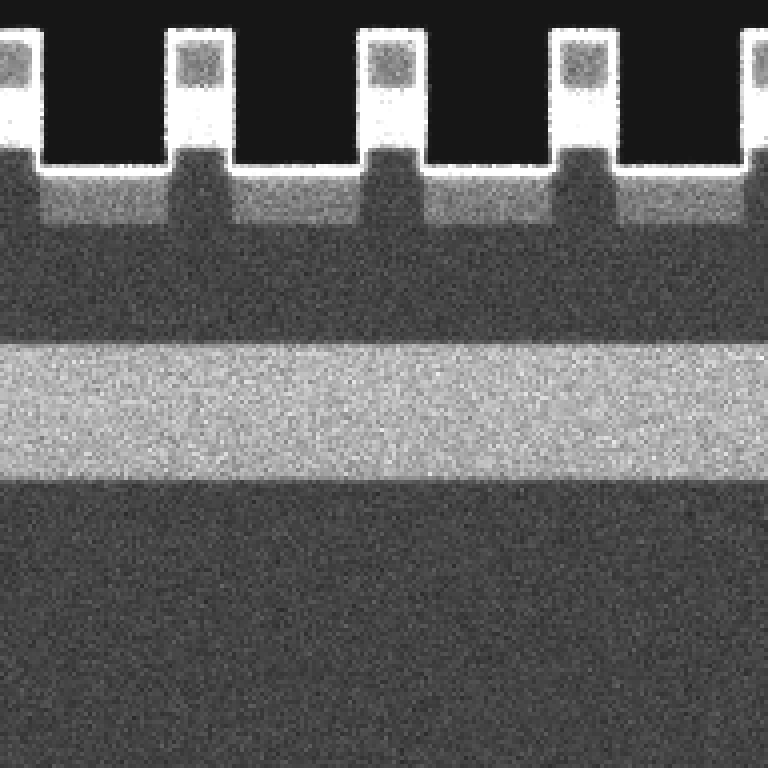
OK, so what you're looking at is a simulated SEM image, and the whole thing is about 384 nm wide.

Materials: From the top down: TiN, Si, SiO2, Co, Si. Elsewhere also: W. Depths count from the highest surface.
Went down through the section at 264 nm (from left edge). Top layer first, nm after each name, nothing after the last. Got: empty 68, TiN 28, Si 60, SiO2 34, Co 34, Si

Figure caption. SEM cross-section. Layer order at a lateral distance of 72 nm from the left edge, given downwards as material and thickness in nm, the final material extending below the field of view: empty 68, TiN 28, Si 60, SiO2 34, Co 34, Si